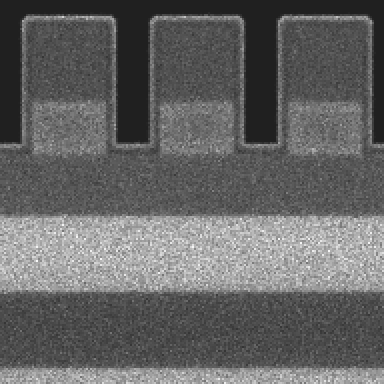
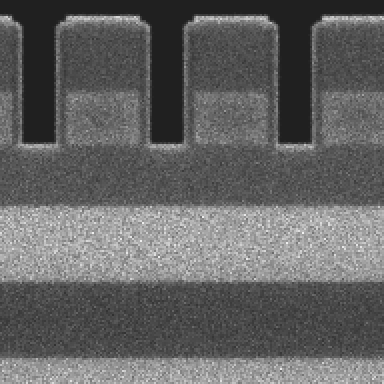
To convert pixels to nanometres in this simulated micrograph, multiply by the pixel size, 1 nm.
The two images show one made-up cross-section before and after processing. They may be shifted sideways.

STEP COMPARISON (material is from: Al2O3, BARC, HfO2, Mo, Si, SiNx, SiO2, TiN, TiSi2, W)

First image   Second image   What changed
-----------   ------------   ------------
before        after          SiNx, removed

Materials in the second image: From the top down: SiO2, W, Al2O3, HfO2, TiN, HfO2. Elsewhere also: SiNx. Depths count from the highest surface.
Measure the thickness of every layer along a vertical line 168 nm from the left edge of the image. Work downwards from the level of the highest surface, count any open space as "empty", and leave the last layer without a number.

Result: empty 128, Al2O3 62, HfO2 76, TiN 76, HfO2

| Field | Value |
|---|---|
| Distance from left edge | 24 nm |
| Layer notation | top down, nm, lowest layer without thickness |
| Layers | empty 128, Al2O3 62, HfO2 76, TiN 76, HfO2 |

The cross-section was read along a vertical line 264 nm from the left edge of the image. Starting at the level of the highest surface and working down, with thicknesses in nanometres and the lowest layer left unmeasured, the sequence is SiO2 76, W 52, Al2O3 62, HfO2 76, TiN 76, HfO2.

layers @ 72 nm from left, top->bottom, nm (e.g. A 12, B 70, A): SiO2 76, W 52, Al2O3 62, HfO2 76, TiN 76, HfO2